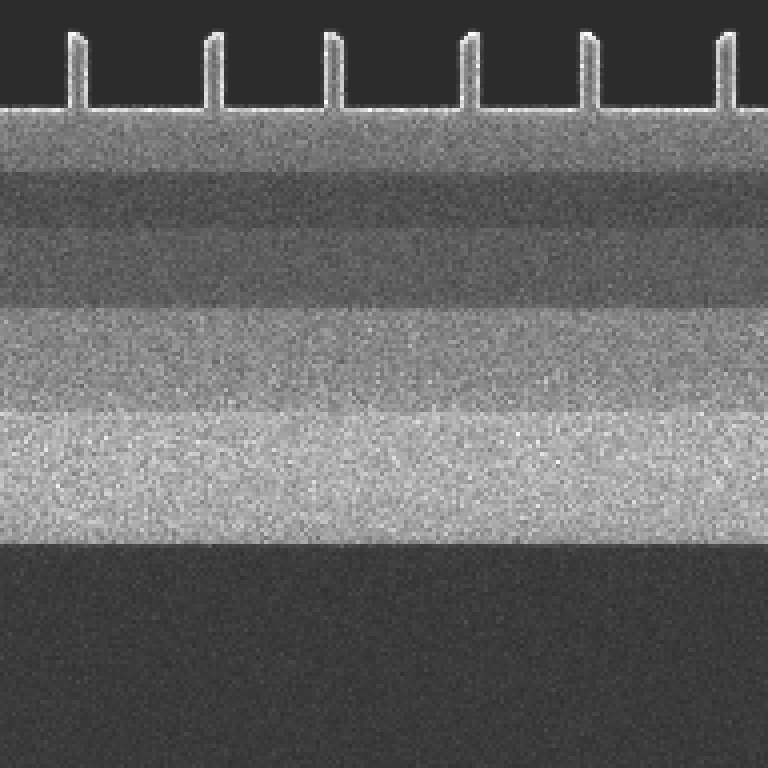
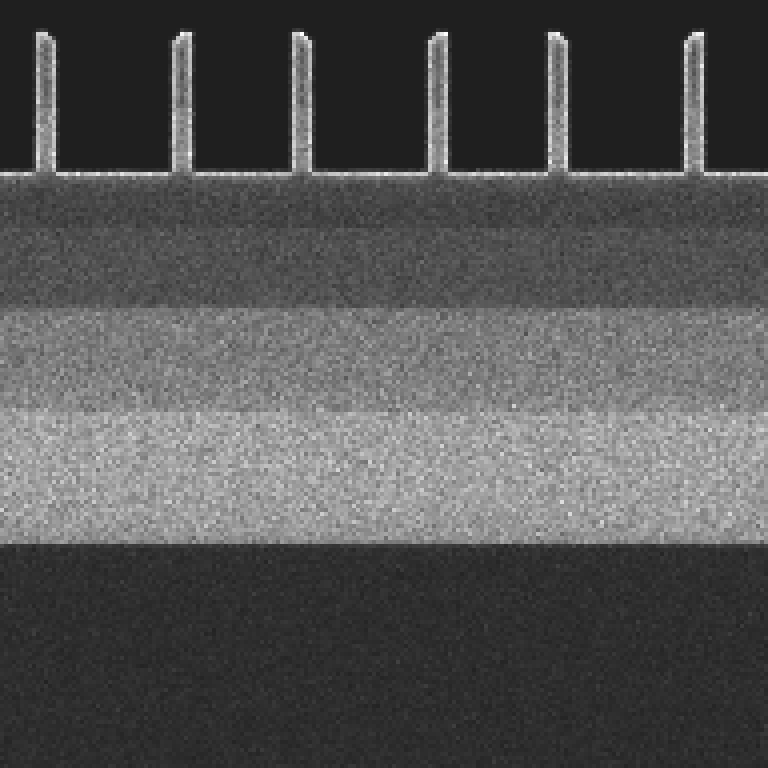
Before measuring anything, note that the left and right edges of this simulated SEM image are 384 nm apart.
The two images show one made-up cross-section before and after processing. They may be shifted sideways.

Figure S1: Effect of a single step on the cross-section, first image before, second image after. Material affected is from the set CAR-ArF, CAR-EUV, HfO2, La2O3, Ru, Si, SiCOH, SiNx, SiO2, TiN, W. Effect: removed Ru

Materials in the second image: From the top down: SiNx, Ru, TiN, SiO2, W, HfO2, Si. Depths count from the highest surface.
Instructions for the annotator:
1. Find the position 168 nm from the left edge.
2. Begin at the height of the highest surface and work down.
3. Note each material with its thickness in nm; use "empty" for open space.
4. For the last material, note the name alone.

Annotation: empty 70, TiN 28, SiO2 40, W 52, HfO2 66, Si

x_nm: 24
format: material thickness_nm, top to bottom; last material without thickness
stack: empty 2, SiNx 36, Ru 32, TiN 28, SiO2 40, W 52, HfO2 66, Si